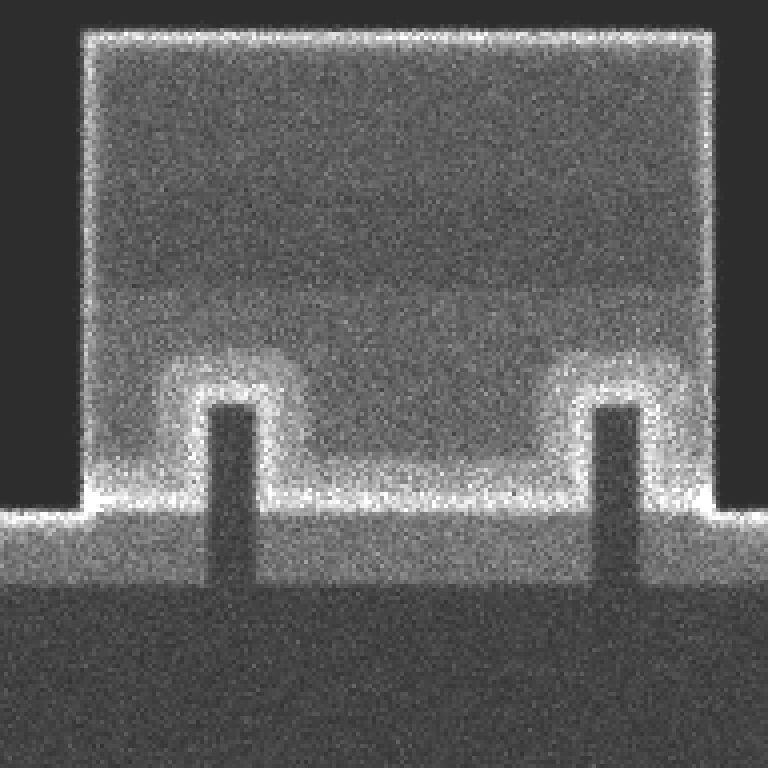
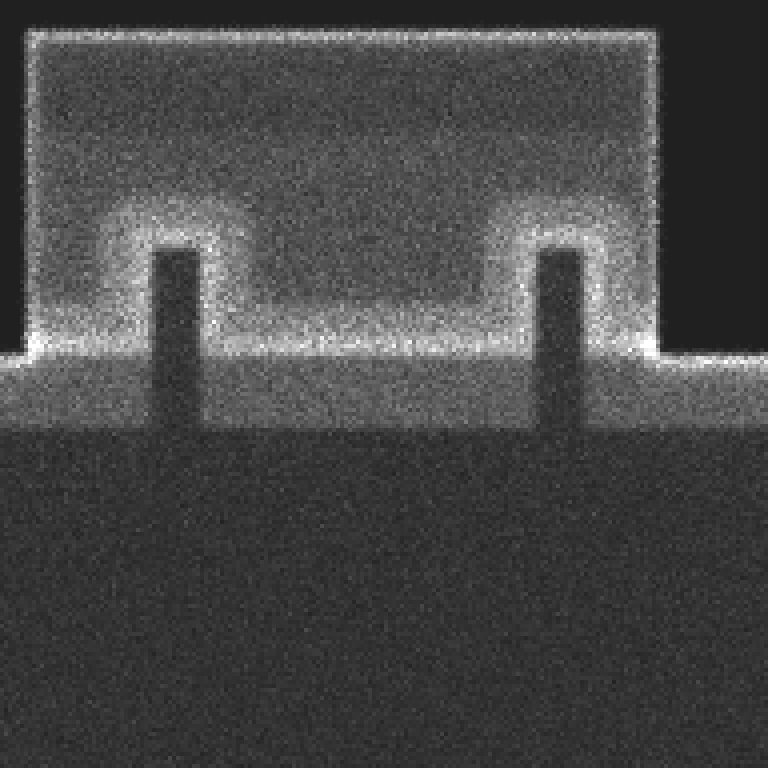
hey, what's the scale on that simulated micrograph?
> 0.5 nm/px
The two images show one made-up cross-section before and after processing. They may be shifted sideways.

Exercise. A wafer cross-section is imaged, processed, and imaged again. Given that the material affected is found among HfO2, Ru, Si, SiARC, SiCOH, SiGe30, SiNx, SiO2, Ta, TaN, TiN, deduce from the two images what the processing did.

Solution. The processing removed SiARC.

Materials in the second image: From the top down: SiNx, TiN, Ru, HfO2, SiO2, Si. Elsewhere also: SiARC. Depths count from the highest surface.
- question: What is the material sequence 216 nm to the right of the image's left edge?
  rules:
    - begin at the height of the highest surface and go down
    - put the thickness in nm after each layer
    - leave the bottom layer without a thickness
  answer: SiNx 50, TiN 86, Ru 16, HfO2 10, SiO2 36, Si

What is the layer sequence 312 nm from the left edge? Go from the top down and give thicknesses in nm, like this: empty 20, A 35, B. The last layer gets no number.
SiNx 50, TiN 40, Ru 62, HfO2 10, SiO2 36, Si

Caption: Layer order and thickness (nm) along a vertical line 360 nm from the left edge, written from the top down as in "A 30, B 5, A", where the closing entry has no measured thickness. empty 162, SiO2 36, Si